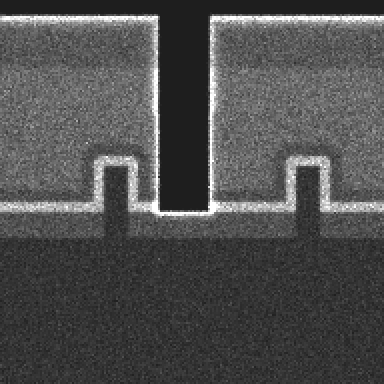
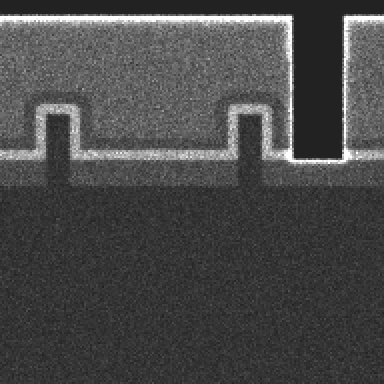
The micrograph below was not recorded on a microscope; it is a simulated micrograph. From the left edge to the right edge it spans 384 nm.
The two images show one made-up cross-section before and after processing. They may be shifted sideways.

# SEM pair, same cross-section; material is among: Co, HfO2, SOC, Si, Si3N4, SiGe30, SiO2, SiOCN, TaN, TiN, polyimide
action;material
removed;SOC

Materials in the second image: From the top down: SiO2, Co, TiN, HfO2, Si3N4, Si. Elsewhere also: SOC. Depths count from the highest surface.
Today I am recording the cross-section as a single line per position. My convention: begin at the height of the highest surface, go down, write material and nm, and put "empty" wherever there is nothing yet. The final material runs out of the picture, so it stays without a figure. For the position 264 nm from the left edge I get SiO2 44, Co 32, TiN 12, HfO2 56, Si3N4 26, Si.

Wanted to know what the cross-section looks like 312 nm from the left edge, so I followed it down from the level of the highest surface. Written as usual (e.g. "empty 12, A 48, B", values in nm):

empty 144, Si3N4 26, Si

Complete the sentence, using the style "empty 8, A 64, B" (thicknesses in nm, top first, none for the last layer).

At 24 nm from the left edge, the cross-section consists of SiO2 44, Co 42, TiN 48, HfO2 10, Si3N4 26, Si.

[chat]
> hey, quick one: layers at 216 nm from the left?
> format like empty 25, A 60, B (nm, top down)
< SiO2 44, Co 42, TiN 48, HfO2 10, Si3N4 26, Si